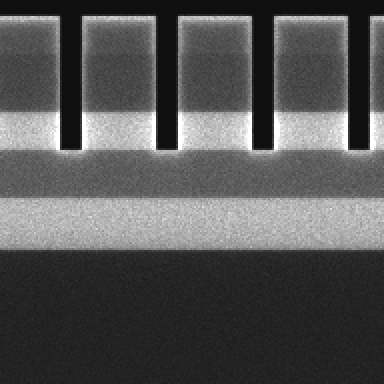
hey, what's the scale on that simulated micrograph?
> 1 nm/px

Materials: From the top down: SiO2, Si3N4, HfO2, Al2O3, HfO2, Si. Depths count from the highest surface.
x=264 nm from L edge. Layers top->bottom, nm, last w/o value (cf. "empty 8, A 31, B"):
empty 134, Al2O3 48, HfO2 52, Si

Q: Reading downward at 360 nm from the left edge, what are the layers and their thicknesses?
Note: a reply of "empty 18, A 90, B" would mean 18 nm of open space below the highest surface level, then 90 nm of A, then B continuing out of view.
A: empty 134, Al2O3 48, HfO2 52, Si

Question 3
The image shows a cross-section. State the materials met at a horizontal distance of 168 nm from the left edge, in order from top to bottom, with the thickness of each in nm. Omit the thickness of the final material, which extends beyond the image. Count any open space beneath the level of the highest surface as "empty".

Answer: empty 134, Al2O3 48, HfO2 52, Si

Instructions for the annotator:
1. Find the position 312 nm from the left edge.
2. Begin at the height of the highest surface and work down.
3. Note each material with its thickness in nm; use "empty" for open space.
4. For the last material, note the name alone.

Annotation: SiO2 38, Si3N4 58, HfO2 38, Al2O3 48, HfO2 52, Si